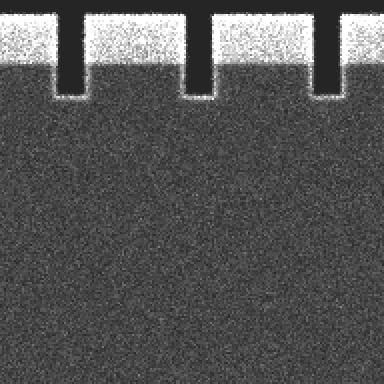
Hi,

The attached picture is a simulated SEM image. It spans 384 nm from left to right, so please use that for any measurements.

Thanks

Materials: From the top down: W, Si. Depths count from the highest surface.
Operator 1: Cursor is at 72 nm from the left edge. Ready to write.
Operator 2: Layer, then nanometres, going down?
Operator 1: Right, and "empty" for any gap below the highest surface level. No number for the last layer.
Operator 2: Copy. empty 80, Si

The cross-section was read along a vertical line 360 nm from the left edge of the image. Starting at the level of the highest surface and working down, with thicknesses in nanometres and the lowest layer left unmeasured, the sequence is W 48, Si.